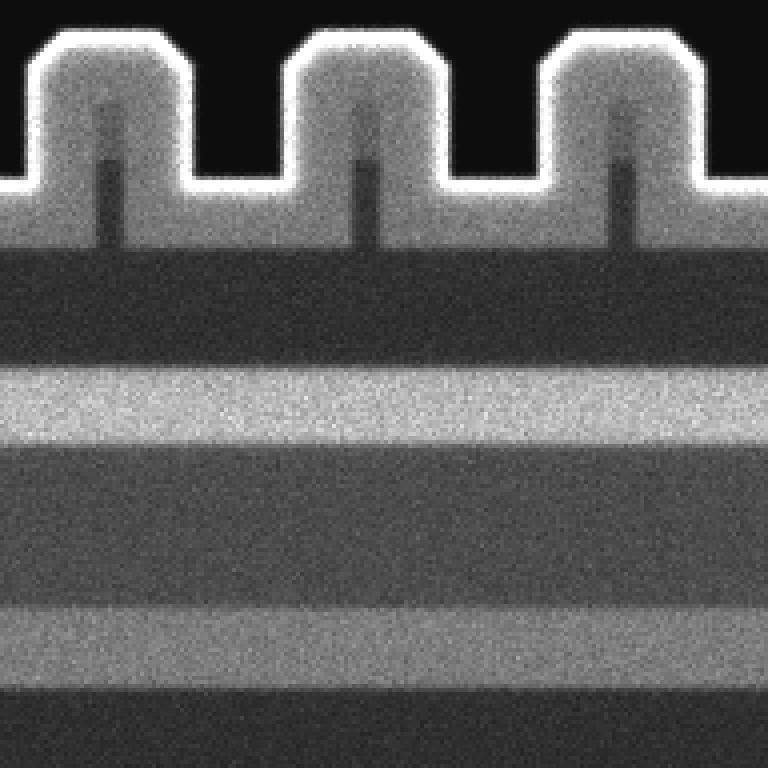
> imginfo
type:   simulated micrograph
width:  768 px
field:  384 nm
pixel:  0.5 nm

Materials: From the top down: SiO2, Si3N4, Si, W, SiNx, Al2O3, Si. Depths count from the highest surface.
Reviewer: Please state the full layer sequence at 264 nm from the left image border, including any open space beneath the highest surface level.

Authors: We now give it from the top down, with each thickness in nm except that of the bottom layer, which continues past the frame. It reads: empty 74, SiO2 34, Si 60, W 38, SiNx 82, Al2O3 40, Si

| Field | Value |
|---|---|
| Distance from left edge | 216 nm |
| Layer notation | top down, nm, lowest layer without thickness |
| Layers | empty 10, SiO2 98, Si 60, W 38, SiNx 82, Al2O3 40, Si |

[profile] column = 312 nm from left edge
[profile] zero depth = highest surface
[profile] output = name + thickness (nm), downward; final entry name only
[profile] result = SiO2 34, Si3N4 30, Si 104, W 38, SiNx 82, Al2O3 40, Si